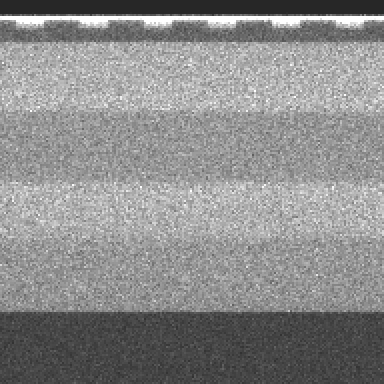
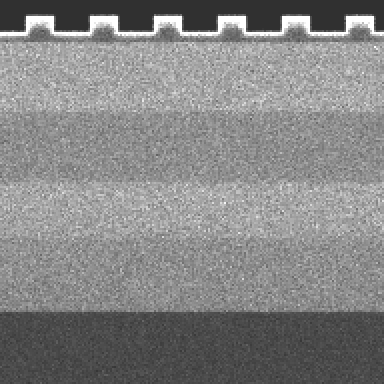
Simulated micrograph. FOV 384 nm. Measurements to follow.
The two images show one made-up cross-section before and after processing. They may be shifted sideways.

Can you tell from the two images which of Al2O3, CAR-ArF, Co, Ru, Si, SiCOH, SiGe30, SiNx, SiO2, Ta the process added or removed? Yes, it removed SiNx.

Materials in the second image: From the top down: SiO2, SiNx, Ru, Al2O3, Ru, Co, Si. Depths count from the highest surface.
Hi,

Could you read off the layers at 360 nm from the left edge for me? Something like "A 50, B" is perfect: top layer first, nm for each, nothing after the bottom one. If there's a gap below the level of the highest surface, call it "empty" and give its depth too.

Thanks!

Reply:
SiO2 12, SiNx 14, Ru 70, Al2O3 70, Ru 56, Co 74, Si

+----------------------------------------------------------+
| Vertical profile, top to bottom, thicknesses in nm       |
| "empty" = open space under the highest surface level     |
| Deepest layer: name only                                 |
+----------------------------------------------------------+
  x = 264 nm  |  empty 16, SiNx 10, Ru 70, Al2O3 70, Ru 56, Co 74, Si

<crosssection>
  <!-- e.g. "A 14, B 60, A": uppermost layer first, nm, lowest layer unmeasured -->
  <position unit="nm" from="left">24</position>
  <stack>empty 16, SiNx 10, Ru 70, Al2O3 70, Ru 56, Co 74, Si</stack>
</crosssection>